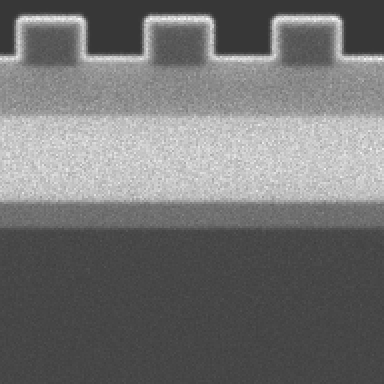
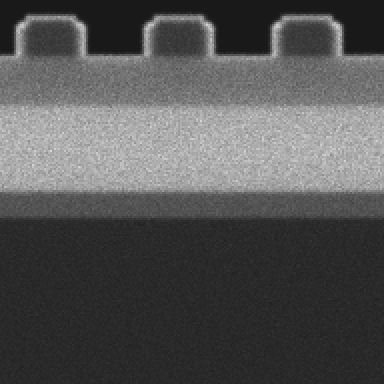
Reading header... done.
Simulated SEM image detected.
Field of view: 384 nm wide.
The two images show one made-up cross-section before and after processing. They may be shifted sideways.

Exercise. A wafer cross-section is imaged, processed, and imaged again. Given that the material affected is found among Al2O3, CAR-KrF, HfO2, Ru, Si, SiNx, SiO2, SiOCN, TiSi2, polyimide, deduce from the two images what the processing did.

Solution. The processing removed SiO2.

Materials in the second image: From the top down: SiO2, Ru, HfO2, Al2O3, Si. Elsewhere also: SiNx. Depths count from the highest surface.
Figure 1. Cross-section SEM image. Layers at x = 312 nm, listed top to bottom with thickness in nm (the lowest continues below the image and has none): SiNx 40, Ru 50, HfO2 86, Al2O3 26, Si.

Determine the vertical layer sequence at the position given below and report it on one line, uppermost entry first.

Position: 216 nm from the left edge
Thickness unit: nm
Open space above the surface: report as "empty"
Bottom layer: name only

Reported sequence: empty 40, Ru 50, HfO2 86, Al2O3 26, Si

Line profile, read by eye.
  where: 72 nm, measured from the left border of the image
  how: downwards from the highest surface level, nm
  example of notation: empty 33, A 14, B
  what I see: SiNx 40, Ru 50, HfO2 86, Al2O3 26, Si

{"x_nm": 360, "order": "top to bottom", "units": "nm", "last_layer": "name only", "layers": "empty 40, Ru 50, HfO2 86, Al2O3 26, Si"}